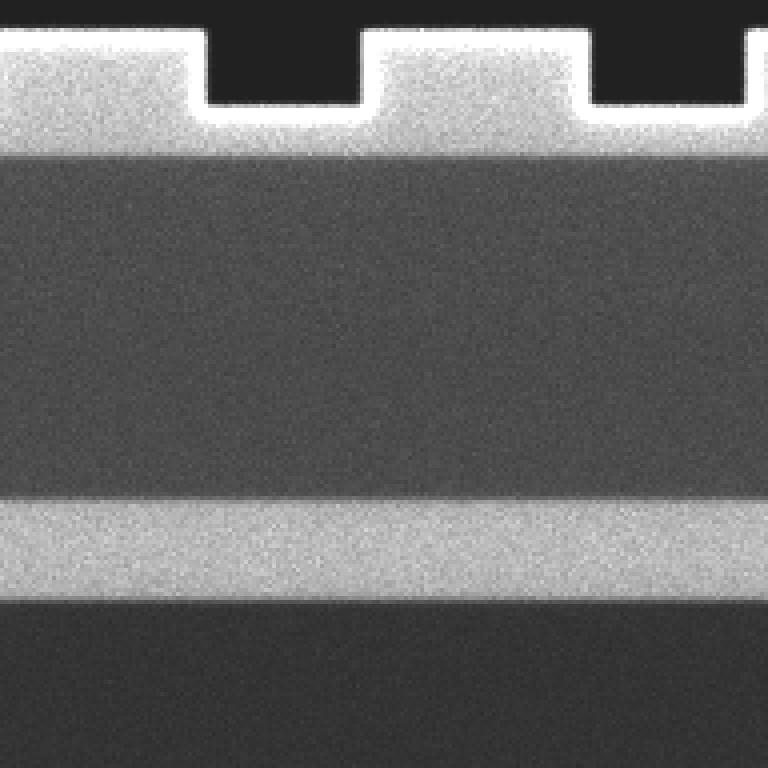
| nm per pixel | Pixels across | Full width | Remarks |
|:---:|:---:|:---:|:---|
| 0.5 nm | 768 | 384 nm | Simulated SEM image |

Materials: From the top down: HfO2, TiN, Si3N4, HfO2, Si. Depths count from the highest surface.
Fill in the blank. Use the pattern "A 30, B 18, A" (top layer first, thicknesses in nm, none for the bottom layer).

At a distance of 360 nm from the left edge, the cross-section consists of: empty 38, HfO2 24, TiN 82, Si3N4 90, HfO2 50, Si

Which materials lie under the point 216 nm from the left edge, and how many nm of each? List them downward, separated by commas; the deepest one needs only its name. HfO2 62, TiN 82, Si3N4 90, HfO2 50, Si